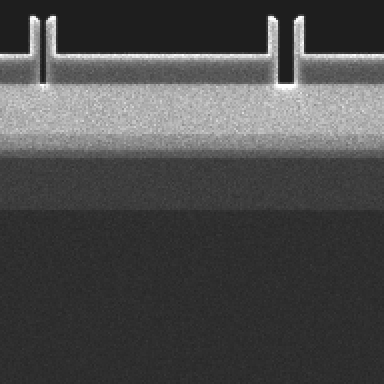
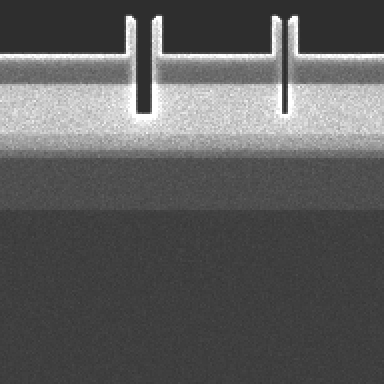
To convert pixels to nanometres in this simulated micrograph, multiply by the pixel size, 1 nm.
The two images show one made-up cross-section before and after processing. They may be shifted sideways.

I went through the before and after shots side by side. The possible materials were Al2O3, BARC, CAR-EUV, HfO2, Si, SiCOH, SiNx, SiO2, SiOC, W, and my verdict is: removed, HfO2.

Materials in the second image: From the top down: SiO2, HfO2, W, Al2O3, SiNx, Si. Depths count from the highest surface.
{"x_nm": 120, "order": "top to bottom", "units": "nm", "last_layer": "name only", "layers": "empty 38, SiO2 30, HfO2 50, W 16, Al2O3 8, SiNx 52, Si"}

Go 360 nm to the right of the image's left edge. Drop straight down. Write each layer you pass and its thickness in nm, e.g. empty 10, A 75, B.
empty 38, SiO2 30, HfO2 50, W 16, Al2O3 8, SiNx 52, Si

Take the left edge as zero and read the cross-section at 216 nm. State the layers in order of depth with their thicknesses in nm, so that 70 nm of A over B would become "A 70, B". empty 38, SiO2 30, HfO2 50, W 16, Al2O3 8, SiNx 52, Si